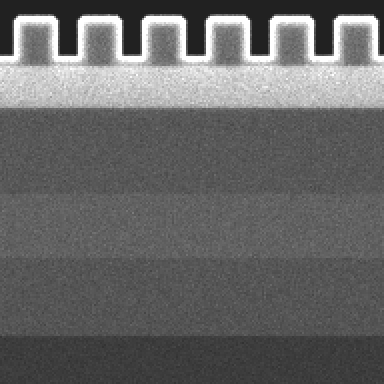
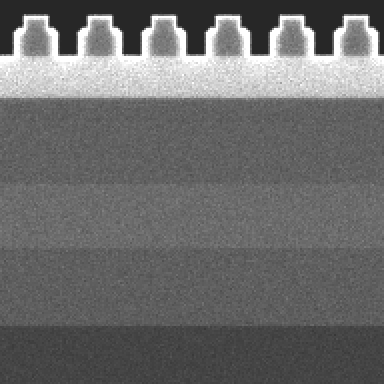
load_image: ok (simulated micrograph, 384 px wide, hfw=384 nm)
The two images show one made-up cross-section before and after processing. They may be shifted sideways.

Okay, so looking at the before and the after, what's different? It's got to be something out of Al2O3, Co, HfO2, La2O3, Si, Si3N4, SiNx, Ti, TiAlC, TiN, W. Al2O3, removed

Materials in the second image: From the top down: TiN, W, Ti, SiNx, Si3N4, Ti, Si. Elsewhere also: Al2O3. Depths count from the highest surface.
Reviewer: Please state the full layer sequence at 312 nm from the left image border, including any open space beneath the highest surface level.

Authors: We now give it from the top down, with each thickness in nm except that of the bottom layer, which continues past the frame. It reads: empty 16, Al2O3 24, W 42, Ti 24, SiNx 62, Si3N4 64, Ti 78, Si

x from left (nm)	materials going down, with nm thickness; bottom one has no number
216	TiN 40, W 42, Ti 24, SiNx 62, Si3N4 64, Ti 78, Si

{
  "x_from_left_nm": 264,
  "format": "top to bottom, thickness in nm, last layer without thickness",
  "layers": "empty 40, W 42, Ti 24, SiNx 62, Si3N4 64, Ti 78, Si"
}